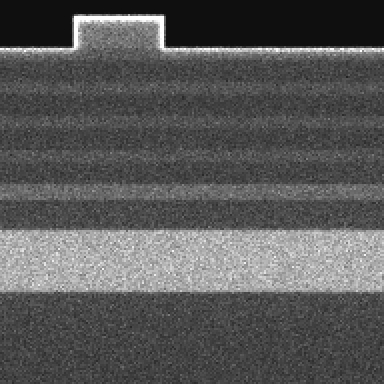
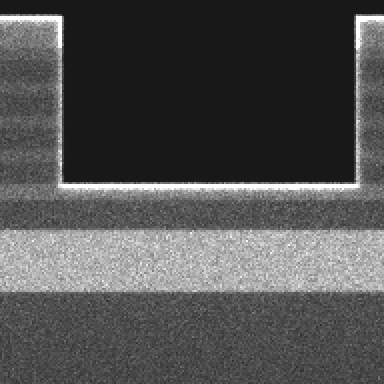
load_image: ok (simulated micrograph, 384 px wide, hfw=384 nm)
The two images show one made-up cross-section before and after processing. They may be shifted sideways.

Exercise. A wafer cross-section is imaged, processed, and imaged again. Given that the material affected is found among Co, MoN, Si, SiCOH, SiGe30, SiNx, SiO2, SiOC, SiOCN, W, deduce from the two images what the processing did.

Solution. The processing removed Si and SiGe30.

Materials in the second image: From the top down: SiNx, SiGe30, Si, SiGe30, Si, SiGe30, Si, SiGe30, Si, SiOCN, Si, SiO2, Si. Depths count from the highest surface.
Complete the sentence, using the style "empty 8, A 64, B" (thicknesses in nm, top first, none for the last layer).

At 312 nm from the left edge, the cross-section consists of empty 168, SiOCN 16, Si 30, SiO2 62, Si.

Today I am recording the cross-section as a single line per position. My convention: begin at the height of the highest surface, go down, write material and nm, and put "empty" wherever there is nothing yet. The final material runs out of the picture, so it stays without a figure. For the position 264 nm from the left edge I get empty 168, SiOCN 16, Si 30, SiO2 62, Si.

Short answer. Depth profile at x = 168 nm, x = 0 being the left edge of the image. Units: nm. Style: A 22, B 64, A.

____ empty 168, SiOCN 16, Si 30, SiO2 62, Si